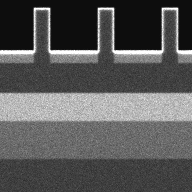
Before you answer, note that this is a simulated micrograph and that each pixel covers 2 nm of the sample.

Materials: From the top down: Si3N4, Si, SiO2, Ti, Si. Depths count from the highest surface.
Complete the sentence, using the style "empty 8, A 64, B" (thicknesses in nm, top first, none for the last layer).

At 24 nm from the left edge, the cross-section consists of empty 86, Si3N4 24, Si 60, SiO2 56, Ti 76, Si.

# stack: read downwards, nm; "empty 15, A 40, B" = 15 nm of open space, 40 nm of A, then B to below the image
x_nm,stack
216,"Si 170, SiO2 56, Ti 76, Si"